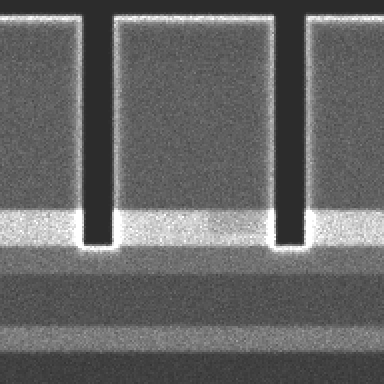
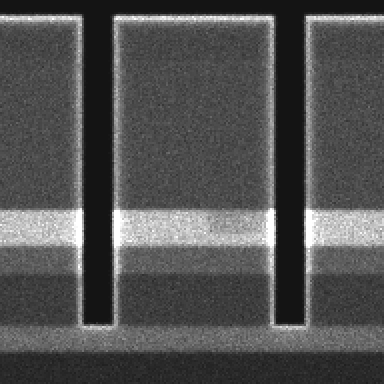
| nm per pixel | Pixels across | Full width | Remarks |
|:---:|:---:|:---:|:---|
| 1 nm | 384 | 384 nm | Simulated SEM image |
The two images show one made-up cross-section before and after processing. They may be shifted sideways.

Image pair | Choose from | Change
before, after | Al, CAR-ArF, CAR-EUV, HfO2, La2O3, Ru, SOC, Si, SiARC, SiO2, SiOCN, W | SiO2 and SiOCN (removed)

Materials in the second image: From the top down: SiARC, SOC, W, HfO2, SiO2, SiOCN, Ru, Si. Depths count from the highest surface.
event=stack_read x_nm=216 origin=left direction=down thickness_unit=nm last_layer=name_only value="SiARC 44, SOC 150, W 24, HfO2 12, SiO2 28, SiOCN 52, Ru 26, Si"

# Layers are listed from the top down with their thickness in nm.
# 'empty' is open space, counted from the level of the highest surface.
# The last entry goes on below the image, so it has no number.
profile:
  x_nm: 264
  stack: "SiARC 44, SOC 150, W 24, HfO2 12, SiO2 28, SiOCN 52, Ru 26, Si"